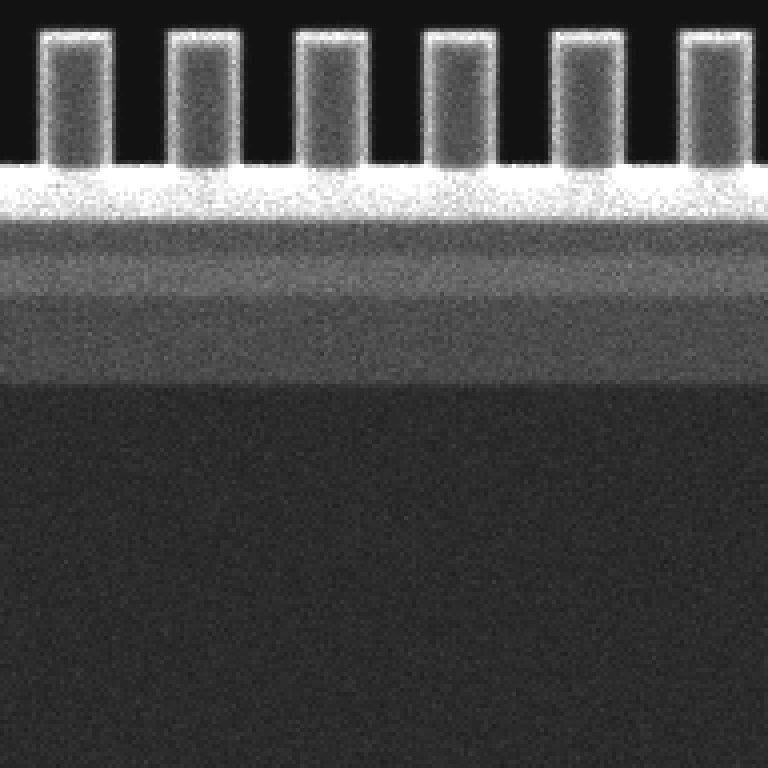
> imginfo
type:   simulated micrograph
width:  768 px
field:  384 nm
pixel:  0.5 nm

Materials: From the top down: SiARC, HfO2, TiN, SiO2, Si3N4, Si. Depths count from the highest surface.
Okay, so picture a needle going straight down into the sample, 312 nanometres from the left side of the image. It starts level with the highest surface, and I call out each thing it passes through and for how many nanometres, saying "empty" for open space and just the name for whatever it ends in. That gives empty 68, HfO2 26, TiN 18, SiO2 20, Si3N4 44, Si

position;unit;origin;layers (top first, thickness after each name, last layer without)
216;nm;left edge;SiARC 68, HfO2 26, TiN 18, SiO2 20, Si3N4 44, Si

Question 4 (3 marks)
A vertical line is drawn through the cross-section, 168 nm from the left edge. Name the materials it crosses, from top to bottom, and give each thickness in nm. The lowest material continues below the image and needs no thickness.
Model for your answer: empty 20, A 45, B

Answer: SiARC 68, HfO2 26, TiN 18, SiO2 20, Si3N4 44, Si